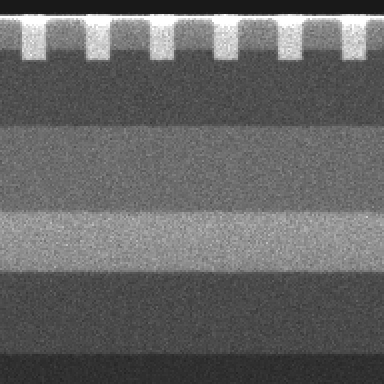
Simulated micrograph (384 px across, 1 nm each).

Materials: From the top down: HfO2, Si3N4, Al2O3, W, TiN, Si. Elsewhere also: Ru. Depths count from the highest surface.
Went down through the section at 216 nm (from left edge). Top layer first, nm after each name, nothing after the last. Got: HfO2 44, Si3N4 66, Al2O3 86, W 60, TiN 82, Si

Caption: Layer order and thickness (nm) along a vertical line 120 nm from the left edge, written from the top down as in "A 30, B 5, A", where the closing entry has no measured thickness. Ru 34, Si3N4 76, Al2O3 86, W 60, TiN 82, Si